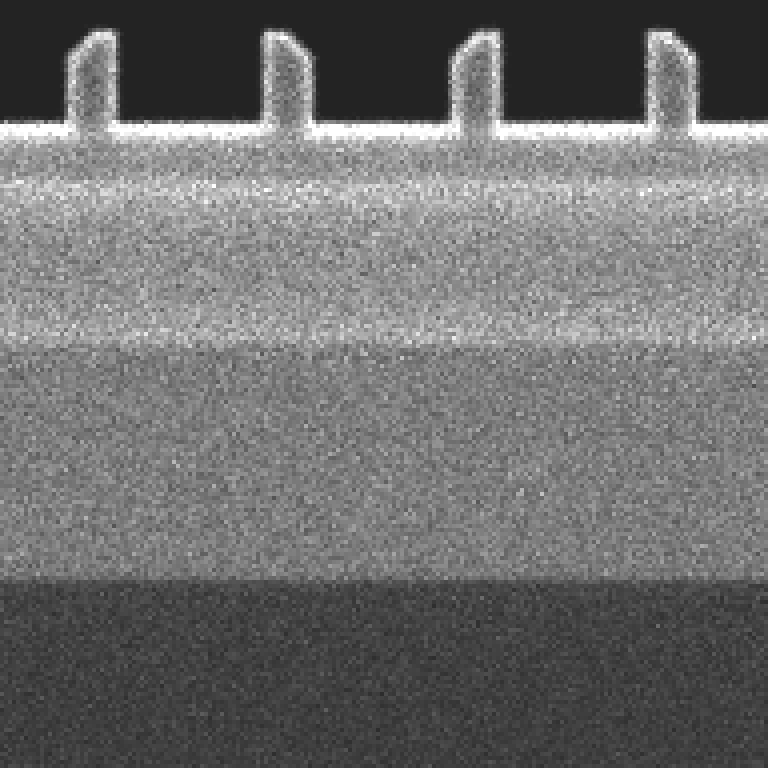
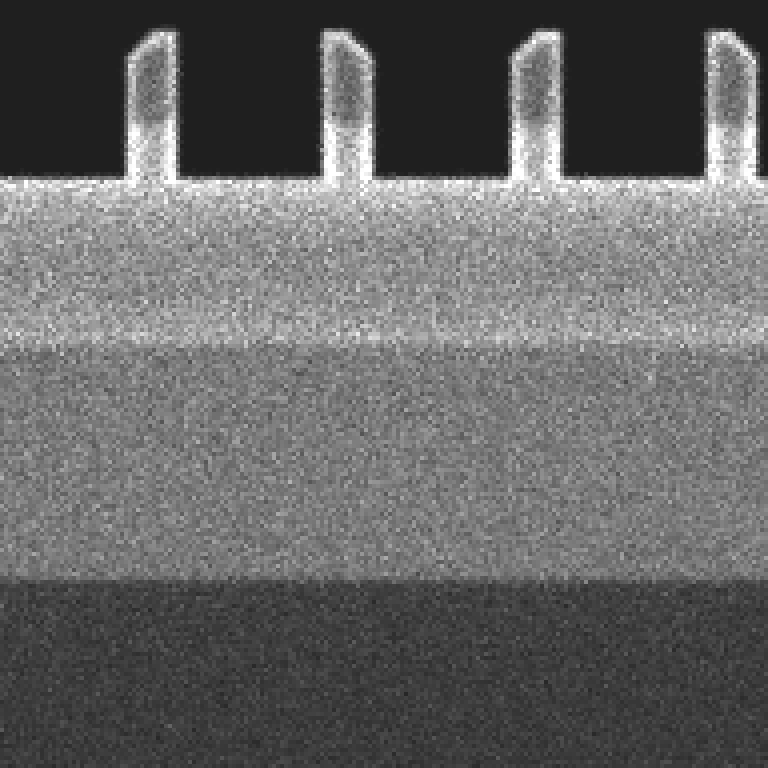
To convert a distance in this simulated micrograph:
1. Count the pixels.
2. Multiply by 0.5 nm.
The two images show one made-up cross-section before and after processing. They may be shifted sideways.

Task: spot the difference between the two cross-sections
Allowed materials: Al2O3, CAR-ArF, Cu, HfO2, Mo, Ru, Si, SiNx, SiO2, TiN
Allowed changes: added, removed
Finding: removed Al2O3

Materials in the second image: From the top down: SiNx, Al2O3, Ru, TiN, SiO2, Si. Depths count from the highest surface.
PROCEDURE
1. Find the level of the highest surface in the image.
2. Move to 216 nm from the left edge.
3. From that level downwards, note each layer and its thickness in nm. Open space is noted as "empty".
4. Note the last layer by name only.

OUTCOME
empty 74, Ru 82, TiN 10, SiO2 108, Si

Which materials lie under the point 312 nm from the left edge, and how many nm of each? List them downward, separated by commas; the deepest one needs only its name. empty 74, Ru 82, TiN 10, SiO2 108, Si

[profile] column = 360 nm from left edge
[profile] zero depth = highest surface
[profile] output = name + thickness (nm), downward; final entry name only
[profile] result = SiNx 46, Al2O3 28, Ru 82, TiN 10, SiO2 108, Si